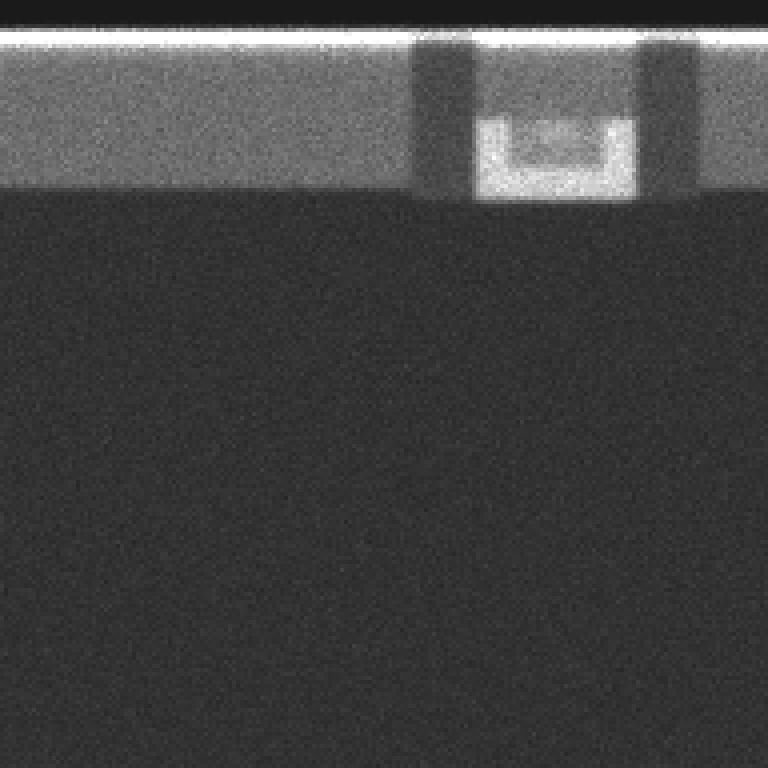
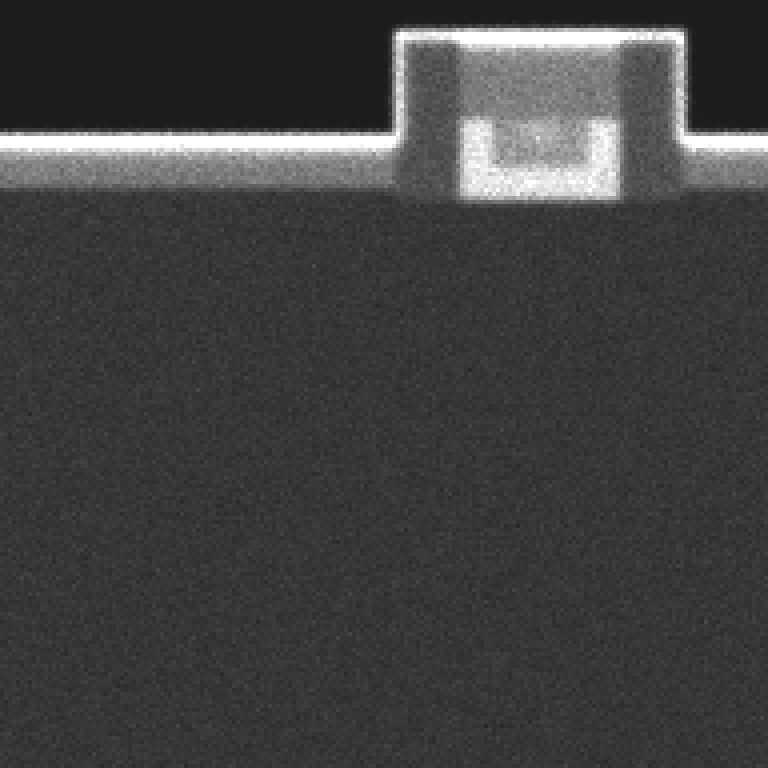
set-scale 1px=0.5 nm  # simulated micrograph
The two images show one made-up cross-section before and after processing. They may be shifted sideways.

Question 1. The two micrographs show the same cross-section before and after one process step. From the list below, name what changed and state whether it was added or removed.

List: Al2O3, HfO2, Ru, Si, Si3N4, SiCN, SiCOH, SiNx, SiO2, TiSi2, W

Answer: SiO2, removed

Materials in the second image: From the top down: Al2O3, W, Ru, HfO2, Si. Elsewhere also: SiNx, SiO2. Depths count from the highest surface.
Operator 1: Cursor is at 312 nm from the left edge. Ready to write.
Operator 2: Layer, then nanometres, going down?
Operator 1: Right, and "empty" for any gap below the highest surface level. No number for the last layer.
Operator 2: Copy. SiNx 84, Si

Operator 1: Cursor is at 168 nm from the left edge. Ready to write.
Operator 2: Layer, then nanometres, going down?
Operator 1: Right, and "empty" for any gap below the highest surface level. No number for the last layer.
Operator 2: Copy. empty 52, SiO2 26, Si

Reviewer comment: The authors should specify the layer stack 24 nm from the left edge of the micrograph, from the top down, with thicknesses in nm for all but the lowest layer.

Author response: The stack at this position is empty 52, SiO2 26, Si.